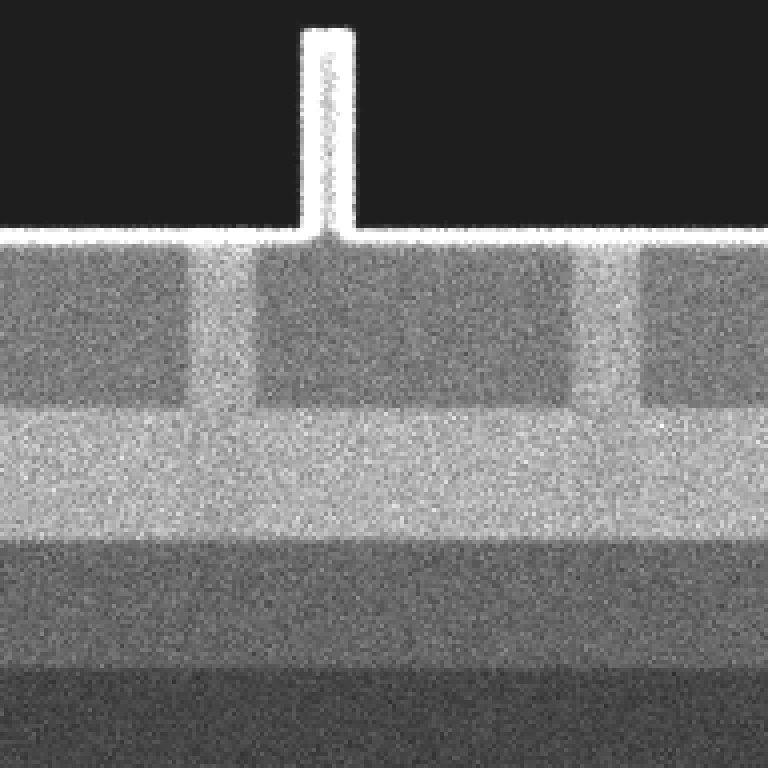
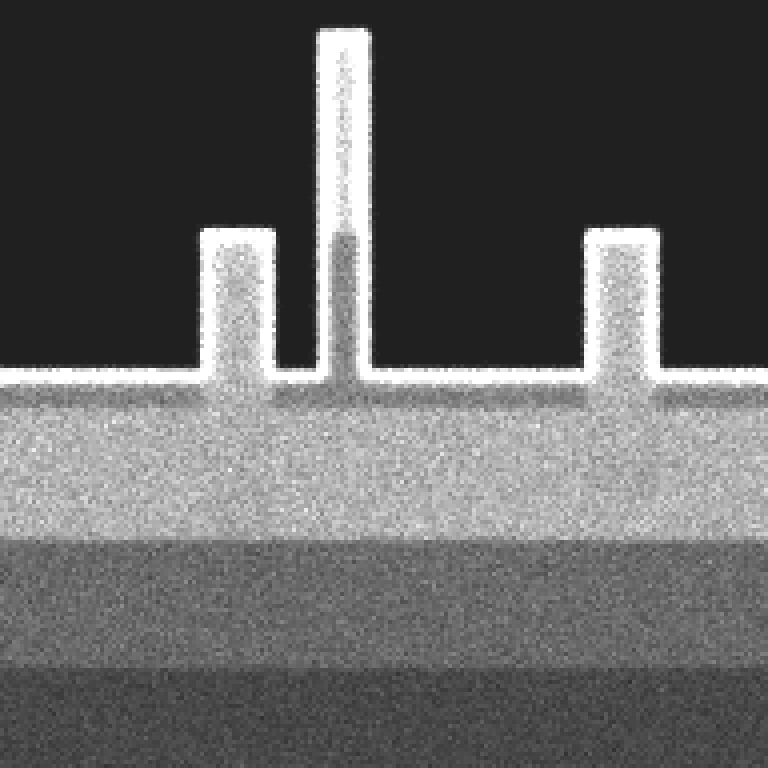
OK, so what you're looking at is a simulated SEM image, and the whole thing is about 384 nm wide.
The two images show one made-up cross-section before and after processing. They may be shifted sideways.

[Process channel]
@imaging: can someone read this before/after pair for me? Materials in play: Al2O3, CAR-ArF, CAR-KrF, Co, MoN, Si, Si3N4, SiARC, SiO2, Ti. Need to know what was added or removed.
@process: Si3N4 removed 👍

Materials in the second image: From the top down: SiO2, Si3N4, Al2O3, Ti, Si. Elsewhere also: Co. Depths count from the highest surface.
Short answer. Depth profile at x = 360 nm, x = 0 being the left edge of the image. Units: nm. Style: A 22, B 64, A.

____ empty 170, Si3N4 18, Al2O3 66, Ti 64, Si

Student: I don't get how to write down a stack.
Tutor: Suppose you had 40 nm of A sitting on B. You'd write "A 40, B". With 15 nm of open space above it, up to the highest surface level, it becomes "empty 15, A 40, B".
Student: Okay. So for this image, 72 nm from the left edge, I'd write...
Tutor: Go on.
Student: empty 170, Si3N4 18, Al2O3 66, Ti 64, Si